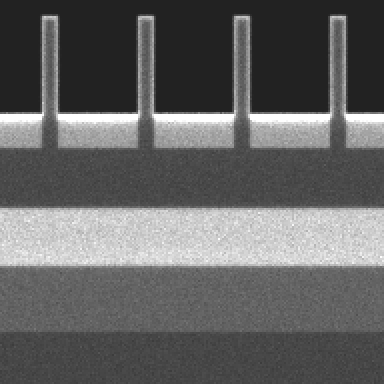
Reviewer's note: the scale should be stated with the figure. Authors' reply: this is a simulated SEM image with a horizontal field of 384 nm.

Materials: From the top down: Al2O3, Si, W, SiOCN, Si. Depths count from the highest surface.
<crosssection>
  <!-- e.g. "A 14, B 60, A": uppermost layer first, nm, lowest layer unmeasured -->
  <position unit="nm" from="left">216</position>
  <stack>empty 98, Al2O3 34, Si 60, W 58, SiOCN 66, Si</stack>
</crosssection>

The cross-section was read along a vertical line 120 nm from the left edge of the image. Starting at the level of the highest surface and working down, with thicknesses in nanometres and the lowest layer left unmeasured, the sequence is empty 98, Al2O3 34, Si 60, W 58, SiOCN 66, Si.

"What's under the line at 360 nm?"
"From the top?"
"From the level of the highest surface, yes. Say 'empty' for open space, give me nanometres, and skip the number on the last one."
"empty 98, Al2O3 34, Si 60, W 58, SiOCN 66, Si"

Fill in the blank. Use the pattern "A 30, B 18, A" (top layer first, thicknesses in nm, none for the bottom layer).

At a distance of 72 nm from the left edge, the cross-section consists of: empty 98, Al2O3 34, Si 60, W 58, SiOCN 66, Si